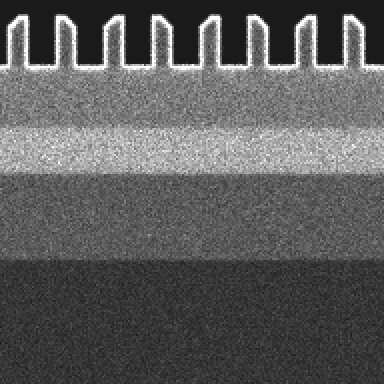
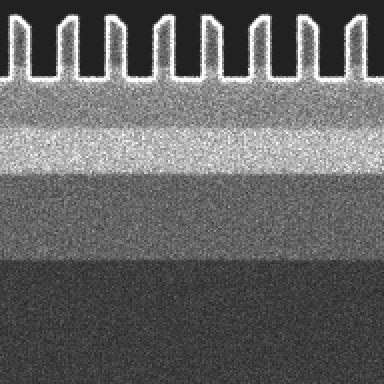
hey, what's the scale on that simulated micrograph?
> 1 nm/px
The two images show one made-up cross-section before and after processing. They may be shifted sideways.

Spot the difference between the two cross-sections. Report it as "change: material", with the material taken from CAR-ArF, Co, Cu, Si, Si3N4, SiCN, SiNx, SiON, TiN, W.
removed: Co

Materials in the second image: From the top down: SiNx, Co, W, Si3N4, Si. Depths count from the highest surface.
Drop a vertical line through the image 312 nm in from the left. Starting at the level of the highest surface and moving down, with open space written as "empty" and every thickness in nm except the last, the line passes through empty 6, SiNx 44, Co 62, W 46, Si3N4 86, Si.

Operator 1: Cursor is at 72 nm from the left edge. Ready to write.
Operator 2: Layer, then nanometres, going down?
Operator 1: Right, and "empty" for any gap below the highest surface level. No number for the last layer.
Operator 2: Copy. SiNx 50, Co 62, W 46, Si3N4 86, Si